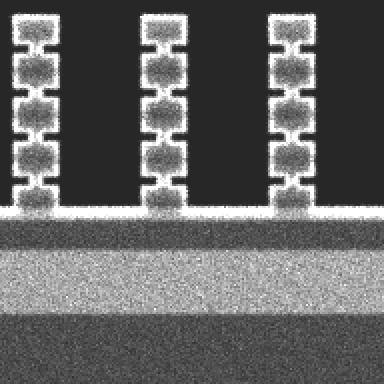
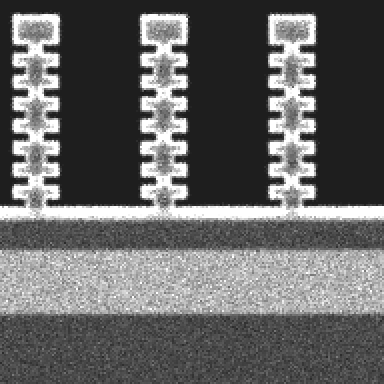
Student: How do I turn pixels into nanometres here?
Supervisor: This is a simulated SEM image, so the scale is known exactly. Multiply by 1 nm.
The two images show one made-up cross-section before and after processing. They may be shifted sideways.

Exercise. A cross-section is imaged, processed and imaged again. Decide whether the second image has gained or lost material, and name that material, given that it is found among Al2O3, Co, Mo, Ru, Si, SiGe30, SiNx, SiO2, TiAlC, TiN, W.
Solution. removed: SiGe30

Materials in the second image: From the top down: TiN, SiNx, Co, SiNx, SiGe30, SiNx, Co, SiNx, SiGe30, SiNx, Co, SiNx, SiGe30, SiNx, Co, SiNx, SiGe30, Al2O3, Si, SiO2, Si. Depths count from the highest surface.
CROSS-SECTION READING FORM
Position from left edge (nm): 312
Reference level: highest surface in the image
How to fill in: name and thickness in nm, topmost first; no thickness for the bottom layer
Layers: TiN 16, SiNx 12, empty 10, SiNx 12, empty 10, SiNx 12, empty 10, SiNx 12, empty 10, SiNx 12, empty 10, SiNx 12, empty 10, SiNx 12, empty 10, SiNx 12, empty 10, Al2O3 12, Si 30, SiO2 64, Si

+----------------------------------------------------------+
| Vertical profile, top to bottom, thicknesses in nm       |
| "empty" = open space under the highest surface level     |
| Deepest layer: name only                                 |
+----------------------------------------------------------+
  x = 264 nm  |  empty 192, Al2O3 12, Si 30, SiO2 64, Si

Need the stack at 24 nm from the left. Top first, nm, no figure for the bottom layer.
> TiN 16, SiNx 12, empty 10, SiNx 12, empty 10, SiNx 12, empty 10, SiNx 12, empty 10, SiNx 12, empty 10, SiNx 12, empty 10, SiNx 12, empty 10, SiNx 12, empty 10, Al2O3 12, Si 30, SiO2 64, Si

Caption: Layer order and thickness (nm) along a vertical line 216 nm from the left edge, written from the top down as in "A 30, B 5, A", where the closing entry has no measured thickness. empty 192, Al2O3 12, Si 30, SiO2 64, Si